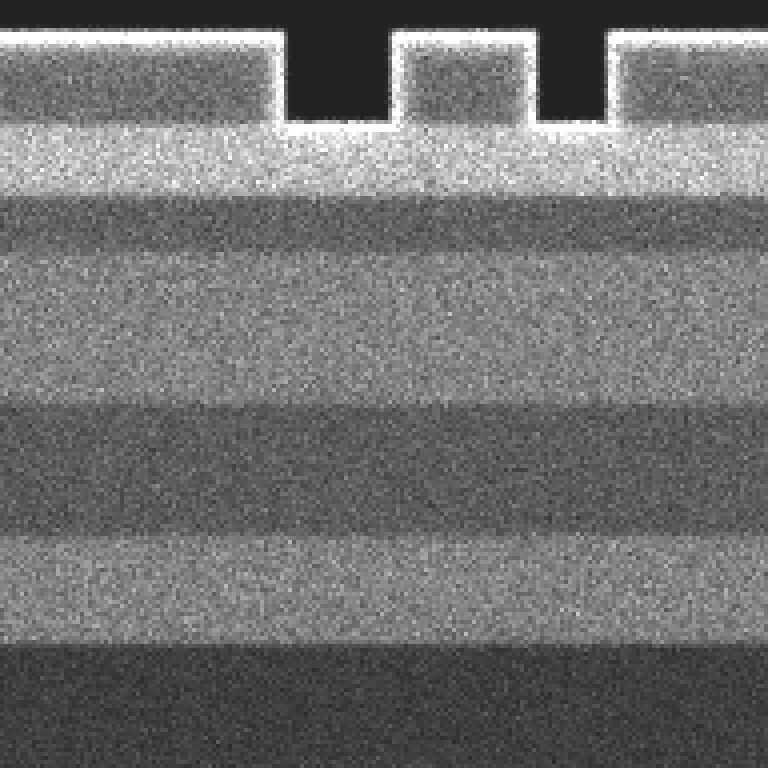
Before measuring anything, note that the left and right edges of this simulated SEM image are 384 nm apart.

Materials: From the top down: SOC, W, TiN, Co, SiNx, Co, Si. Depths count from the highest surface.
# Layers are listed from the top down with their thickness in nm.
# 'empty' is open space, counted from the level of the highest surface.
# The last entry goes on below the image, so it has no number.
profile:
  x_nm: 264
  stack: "SOC 46, W 36, TiN 28, Co 76, SiNx 66, Co 54, Si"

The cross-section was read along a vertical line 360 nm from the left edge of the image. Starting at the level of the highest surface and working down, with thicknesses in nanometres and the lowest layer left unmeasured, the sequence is SOC 46, W 36, TiN 28, Co 76, SiNx 66, Co 54, Si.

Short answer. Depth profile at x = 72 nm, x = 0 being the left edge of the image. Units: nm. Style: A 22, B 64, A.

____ SOC 46, W 36, TiN 28, Co 76, SiNx 66, Co 54, Si